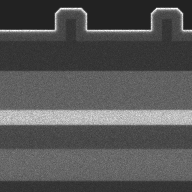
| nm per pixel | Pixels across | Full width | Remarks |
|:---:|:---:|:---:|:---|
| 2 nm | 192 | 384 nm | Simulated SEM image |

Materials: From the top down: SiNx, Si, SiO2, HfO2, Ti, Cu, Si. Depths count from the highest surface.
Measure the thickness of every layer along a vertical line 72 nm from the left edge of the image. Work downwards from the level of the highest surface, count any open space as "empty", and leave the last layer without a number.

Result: empty 44, SiNx 22, Si 60, SiO2 78, HfO2 30, Ti 48, Cu 64, Si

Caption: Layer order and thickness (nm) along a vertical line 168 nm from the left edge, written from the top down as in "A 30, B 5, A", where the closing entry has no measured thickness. empty 6, SiNx 60, Si 60, SiO2 78, HfO2 30, Ti 48, Cu 64, Si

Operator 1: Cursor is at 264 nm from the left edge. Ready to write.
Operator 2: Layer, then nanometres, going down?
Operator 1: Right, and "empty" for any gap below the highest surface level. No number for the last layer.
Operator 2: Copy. empty 44, SiNx 22, Si 60, SiO2 78, HfO2 30, Ti 48, Cu 64, Si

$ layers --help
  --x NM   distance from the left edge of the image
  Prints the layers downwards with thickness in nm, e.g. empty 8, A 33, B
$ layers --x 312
SiNx 66, Si 60, SiO2 78, HfO2 30, Ti 48, Cu 64, Si